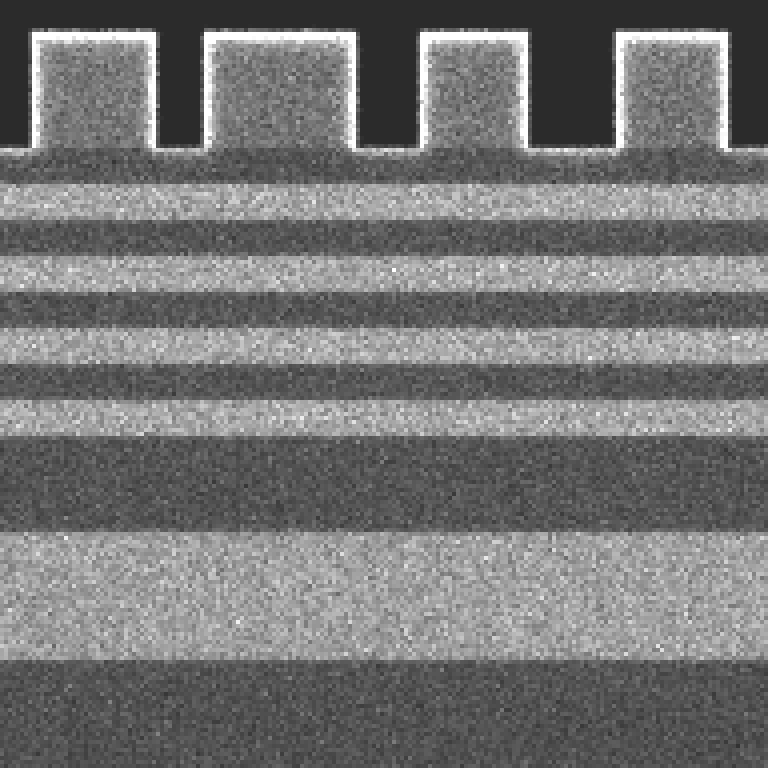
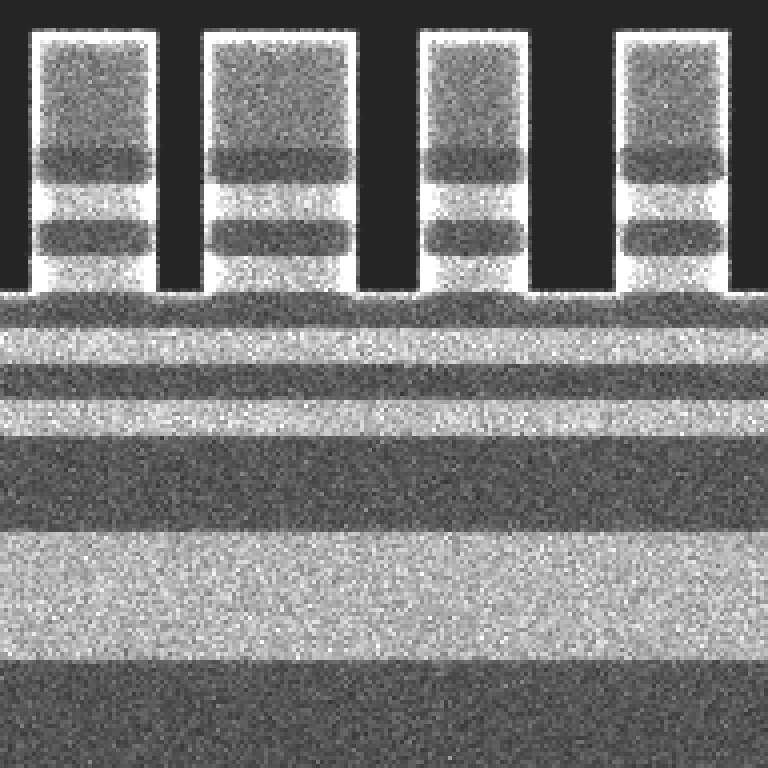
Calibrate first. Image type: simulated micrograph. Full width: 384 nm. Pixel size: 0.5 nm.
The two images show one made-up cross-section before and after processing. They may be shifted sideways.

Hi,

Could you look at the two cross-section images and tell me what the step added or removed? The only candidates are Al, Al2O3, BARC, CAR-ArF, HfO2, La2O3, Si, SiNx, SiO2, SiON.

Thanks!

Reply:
removed Al2O3 and Si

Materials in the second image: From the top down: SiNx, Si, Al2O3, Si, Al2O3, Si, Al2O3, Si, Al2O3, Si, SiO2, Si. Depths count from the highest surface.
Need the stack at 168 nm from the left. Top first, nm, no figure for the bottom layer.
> SiNx 58, Si 18, Al2O3 18, Si 18, Al2O3 18, Si 18, Al2O3 18, Si 18, Al2O3 18, Si 48, SiO2 64, Si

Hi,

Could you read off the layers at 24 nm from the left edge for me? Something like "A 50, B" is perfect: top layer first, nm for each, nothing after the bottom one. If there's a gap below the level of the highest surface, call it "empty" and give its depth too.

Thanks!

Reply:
SiNx 58, Si 18, Al2O3 18, Si 18, Al2O3 18, Si 18, Al2O3 18, Si 18, Al2O3 18, Si 48, SiO2 64, Si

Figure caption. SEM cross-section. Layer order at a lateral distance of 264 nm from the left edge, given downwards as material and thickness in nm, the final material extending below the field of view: empty 130, Si 18, Al2O3 18, Si 18, Al2O3 18, Si 48, SiO2 64, Si